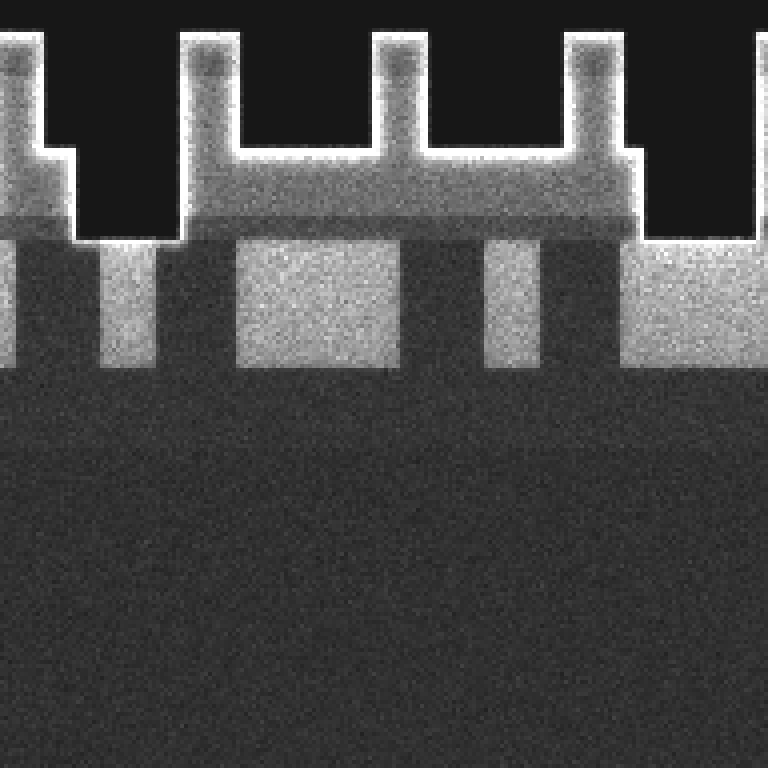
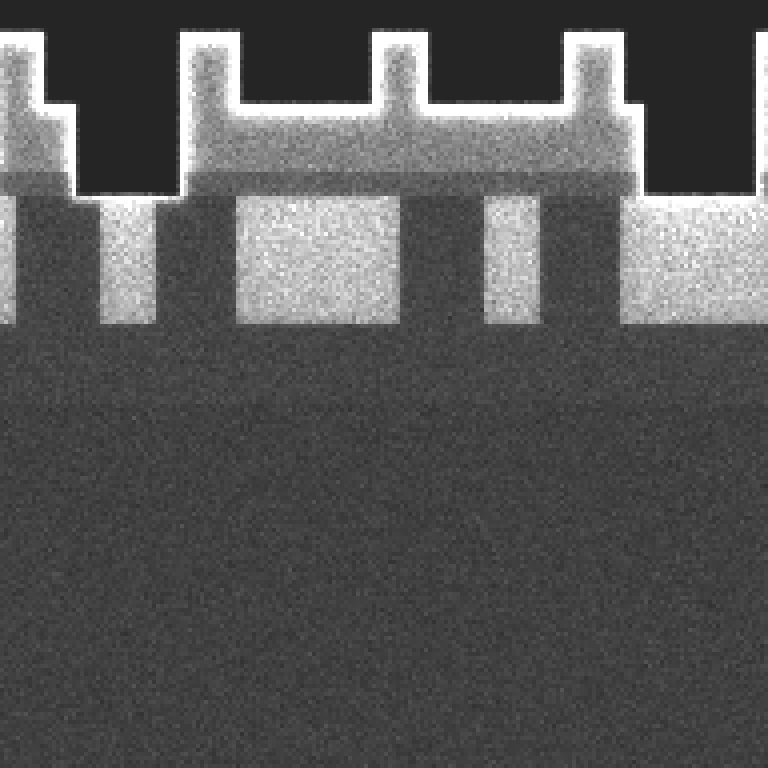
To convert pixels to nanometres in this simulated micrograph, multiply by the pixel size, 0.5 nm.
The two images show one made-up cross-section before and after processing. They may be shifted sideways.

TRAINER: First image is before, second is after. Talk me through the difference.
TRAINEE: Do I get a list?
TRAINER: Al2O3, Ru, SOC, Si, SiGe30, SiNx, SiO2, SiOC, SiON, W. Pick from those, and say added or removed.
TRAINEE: removed: SOC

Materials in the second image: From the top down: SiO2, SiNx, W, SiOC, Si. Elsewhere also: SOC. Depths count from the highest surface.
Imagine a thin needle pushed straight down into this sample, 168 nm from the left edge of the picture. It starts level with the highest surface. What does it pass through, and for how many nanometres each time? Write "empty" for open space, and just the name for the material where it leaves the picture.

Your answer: empty 36, SiO2 34, SiNx 12, W 64, SiOC 40, Si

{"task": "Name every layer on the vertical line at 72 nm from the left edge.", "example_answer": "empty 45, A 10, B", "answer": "empty 82, W 64, SiOC 40, Si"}